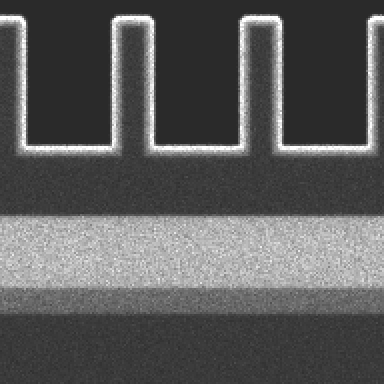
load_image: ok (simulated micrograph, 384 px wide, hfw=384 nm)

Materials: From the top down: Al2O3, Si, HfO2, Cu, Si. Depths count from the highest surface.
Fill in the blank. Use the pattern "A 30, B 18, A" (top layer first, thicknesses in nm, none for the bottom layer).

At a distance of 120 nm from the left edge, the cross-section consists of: Al2O3 140, Si 60, HfO2 72, Cu 26, Si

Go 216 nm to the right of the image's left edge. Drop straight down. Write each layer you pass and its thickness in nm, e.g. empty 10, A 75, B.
empty 130, Al2O3 10, Si 60, HfO2 72, Cu 26, Si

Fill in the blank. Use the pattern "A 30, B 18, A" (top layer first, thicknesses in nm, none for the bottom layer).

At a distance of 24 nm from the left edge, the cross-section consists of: empty 4, Al2O3 136, Si 60, HfO2 72, Cu 26, Si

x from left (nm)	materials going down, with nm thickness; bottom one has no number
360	empty 130, Al2O3 10, Si 60, HfO2 72, Cu 26, Si